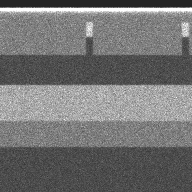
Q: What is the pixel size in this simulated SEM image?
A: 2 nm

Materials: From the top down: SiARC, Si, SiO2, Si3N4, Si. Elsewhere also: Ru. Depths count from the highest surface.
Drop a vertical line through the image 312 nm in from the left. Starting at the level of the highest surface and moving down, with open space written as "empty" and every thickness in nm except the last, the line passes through SiARC 94, Si 60, SiO2 72, Si3N4 52, Si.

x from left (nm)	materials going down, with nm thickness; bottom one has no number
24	SiARC 94, Si 60, SiO2 72, Si3N4 52, Si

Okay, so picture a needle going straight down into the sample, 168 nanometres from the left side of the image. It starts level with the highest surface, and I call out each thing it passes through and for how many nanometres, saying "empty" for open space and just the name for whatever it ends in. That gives SiARC 94, Si 60, SiO2 72, Si3N4 52, Si